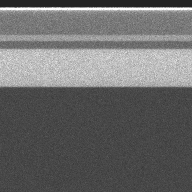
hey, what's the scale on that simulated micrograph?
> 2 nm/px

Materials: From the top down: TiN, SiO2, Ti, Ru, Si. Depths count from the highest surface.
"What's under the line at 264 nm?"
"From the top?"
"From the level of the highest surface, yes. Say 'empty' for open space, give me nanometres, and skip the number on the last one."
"TiN 54, SiO2 12, Ti 16, Ru 76, Si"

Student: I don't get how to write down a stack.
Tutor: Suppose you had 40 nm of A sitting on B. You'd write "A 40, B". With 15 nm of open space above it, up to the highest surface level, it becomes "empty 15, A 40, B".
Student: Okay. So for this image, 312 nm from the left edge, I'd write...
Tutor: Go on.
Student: TiN 54, SiO2 12, Ti 16, Ru 76, Si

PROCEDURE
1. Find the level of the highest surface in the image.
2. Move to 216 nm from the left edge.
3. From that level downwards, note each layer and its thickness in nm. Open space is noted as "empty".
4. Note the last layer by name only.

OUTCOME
TiN 54, SiO2 12, Ti 16, Ru 76, Si